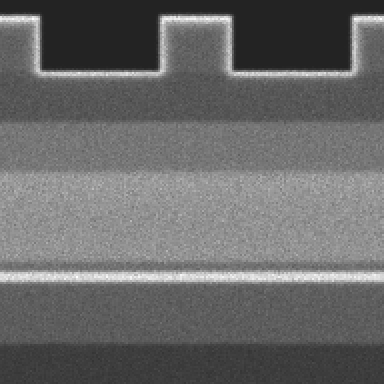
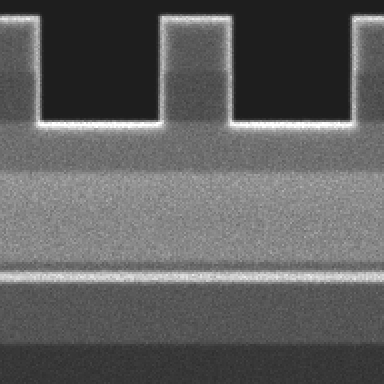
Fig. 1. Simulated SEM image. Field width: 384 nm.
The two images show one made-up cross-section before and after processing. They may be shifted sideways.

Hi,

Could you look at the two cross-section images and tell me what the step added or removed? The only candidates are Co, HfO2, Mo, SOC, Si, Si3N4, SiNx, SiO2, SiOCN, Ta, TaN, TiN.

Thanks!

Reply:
removed SiNx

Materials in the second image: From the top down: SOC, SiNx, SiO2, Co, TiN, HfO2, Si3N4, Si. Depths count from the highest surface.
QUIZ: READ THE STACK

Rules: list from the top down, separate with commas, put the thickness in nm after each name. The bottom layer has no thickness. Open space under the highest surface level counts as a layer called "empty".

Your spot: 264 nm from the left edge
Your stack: empty 106, SiO2 50, Co 90, TiN 10, HfO2 10, Si3N4 62, Si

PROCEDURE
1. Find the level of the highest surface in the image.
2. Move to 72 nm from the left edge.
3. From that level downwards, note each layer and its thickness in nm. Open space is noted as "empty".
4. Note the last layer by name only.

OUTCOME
empty 106, SiO2 50, Co 90, TiN 10, HfO2 10, Si3N4 62, Si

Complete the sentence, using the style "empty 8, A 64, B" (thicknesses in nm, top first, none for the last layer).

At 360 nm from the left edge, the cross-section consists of SOC 56, SiNx 50, SiO2 50, Co 90, TiN 10, HfO2 10, Si3N4 62, Si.